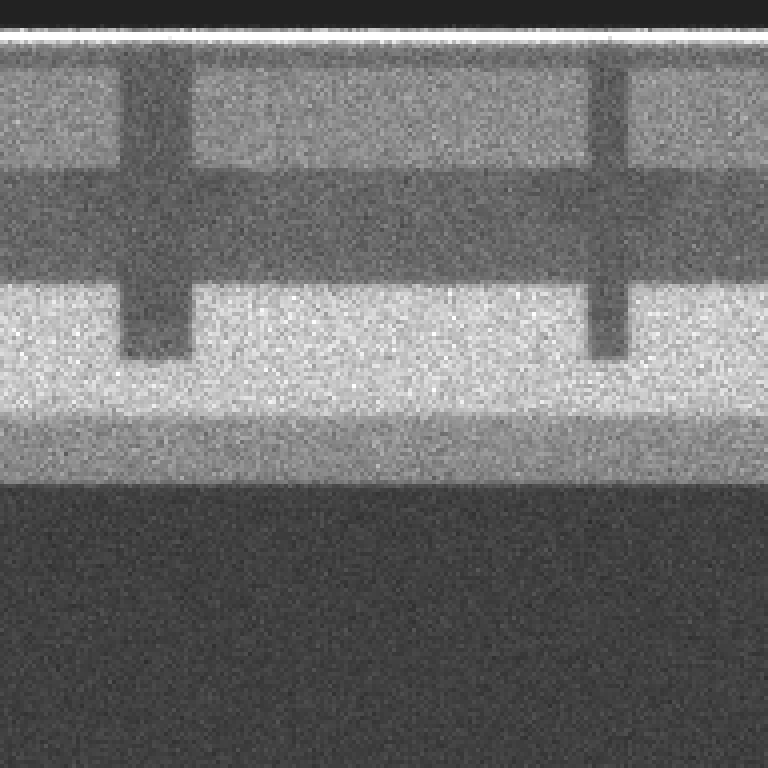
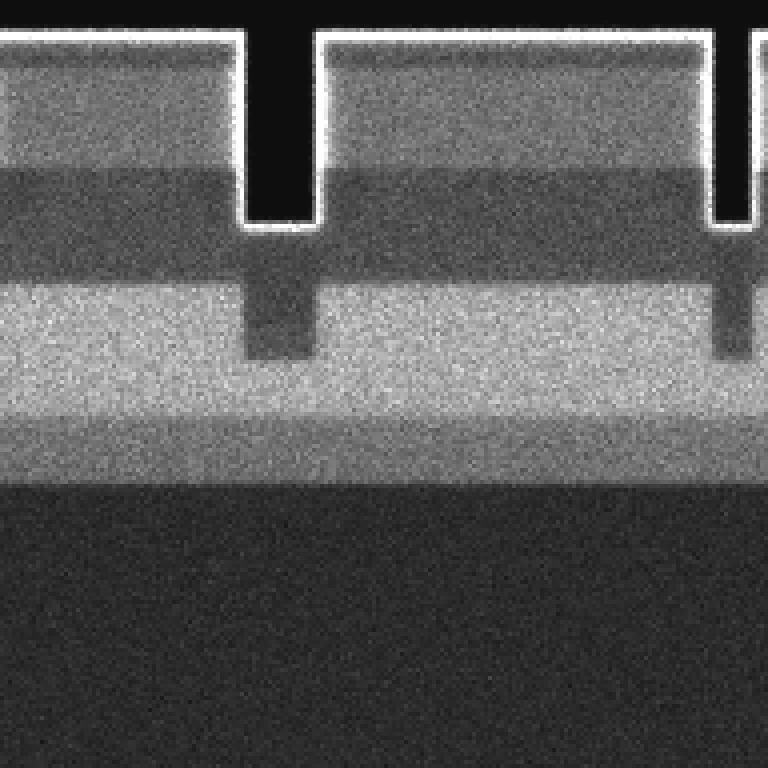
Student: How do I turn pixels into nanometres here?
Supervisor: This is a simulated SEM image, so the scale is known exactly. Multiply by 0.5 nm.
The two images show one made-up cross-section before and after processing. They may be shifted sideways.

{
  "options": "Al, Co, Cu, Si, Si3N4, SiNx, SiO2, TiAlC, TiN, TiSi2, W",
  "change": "removed",
  "material": "SiNx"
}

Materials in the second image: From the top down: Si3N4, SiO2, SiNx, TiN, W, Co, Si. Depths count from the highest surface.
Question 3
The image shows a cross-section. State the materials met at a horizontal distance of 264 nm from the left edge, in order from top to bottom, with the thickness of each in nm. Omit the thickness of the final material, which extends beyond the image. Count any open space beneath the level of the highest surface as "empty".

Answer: Si3N4 18, SiO2 50, TiN 58, W 66, Co 34, Si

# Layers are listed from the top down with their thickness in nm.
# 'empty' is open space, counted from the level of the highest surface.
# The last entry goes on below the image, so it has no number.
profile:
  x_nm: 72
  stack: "Si3N4 18, SiO2 50, TiN 58, W 66, Co 34, Si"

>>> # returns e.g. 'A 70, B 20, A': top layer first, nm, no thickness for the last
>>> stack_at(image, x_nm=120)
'Si3N4 18, SiO2 50, SiNx 28, TiN 30, W 66, Co 34, Si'